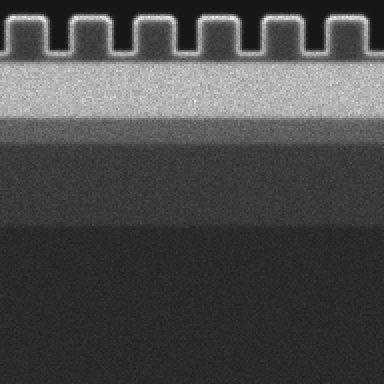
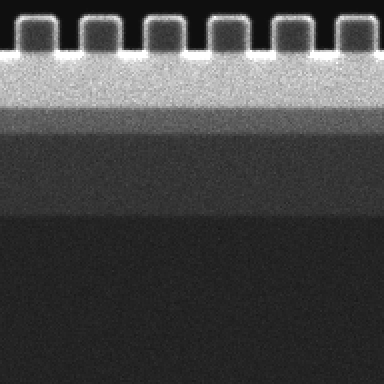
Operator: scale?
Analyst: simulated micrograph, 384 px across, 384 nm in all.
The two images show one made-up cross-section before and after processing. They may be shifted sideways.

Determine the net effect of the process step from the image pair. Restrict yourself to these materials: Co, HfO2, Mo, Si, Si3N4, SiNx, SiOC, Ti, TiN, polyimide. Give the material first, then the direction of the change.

Si3N4: removed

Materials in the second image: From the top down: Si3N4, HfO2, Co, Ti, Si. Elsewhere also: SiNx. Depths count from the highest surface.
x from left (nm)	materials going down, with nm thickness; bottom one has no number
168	SiNx 36, HfO2 56, Co 26, Ti 82, Si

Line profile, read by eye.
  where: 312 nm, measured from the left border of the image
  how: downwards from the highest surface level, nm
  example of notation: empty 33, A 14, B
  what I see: empty 4, Si3N4 32, HfO2 56, Co 26, Ti 82, Si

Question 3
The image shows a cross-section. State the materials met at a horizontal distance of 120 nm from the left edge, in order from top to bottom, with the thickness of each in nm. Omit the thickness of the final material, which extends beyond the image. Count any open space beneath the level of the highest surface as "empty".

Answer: empty 4, Si3N4 32, HfO2 56, Co 26, Ti 82, Si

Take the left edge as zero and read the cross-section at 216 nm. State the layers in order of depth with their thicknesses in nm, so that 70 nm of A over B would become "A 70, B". Si3N4 36, HfO2 56, Co 26, Ti 82, Si